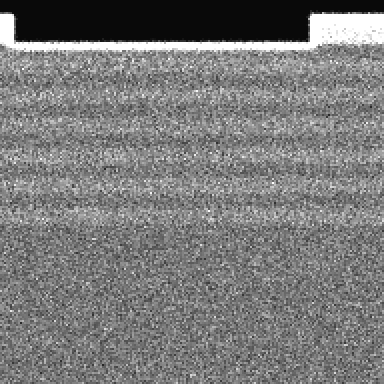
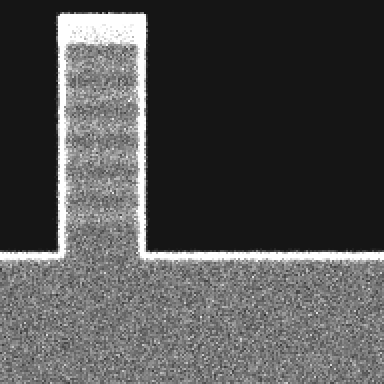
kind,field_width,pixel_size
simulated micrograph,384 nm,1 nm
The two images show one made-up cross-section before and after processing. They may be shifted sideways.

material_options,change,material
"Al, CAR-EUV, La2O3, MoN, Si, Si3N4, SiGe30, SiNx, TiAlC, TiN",removed,Si and SiGe30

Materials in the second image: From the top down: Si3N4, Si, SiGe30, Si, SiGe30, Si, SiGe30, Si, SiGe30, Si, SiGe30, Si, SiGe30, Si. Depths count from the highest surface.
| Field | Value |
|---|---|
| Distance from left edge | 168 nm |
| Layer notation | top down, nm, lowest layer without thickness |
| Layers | empty 238, Si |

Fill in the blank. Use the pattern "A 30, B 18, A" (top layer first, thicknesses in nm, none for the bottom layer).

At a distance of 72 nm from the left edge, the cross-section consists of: Si3N4 28, Si 14, SiGe30 16, Si 14, SiGe30 16, Si 14, SiGe30 16, Si 14, SiGe30 16, Si 14, SiGe30 16, Si 14, SiGe30 16, Si